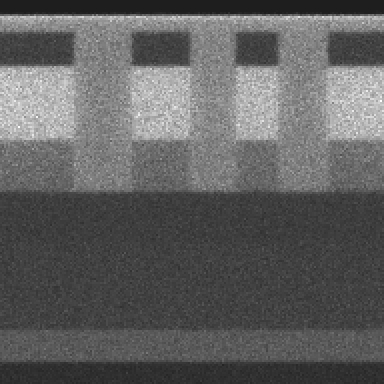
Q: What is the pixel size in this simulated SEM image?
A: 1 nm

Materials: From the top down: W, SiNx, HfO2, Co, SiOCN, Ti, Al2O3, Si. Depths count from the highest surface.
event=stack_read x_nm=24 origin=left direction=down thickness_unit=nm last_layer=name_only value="W 16, SiNx 34, HfO2 74, Co 52, SiOCN 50, Ti 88, Al2O3 32, Si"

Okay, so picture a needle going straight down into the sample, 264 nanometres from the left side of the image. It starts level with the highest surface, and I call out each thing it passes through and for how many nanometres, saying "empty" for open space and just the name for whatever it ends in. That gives W 16, SiNx 34, HfO2 74, Co 52, SiOCN 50, Ti 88, Al2O3 32, Si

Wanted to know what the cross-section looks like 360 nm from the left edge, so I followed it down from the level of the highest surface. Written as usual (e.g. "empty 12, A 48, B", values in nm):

W 16, SiNx 34, HfO2 74, Co 52, SiOCN 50, Ti 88, Al2O3 32, Si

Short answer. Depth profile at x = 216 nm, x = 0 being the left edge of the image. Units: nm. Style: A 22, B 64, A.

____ W 176, SiOCN 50, Ti 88, Al2O3 32, Si